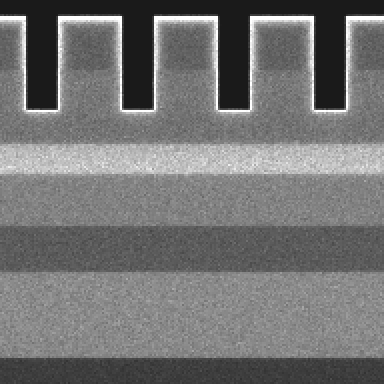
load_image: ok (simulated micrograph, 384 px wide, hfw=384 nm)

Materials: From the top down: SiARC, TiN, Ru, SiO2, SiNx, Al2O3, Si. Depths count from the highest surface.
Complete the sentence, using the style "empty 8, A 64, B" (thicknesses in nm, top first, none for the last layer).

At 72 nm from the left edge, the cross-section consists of SiARC 54, TiN 74, Ru 30, SiO2 52, SiNx 46, Al2O3 86, Si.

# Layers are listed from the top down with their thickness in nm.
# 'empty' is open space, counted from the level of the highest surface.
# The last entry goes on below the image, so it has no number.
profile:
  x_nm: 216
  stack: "SiARC 54, TiN 74, Ru 30, SiO2 52, SiNx 46, Al2O3 86, Si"